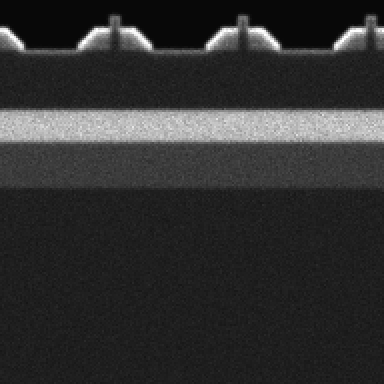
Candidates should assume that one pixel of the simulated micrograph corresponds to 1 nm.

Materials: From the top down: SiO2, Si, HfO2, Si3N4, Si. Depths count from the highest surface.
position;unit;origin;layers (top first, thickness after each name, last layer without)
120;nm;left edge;empty 12, SiO2 22, Si 60, HfO2 32, Si3N4 46, Si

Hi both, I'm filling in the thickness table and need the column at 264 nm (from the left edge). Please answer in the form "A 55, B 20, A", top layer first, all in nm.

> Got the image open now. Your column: empty 14, SiO2 20, Si 60, HfO2 32, Si3N4 46, Si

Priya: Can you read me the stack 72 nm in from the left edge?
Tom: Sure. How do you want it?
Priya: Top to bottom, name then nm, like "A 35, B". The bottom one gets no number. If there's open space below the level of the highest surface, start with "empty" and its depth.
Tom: empty 34, Si 60, HfO2 32, Si3N4 46, Si